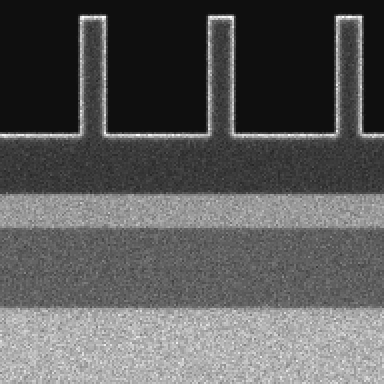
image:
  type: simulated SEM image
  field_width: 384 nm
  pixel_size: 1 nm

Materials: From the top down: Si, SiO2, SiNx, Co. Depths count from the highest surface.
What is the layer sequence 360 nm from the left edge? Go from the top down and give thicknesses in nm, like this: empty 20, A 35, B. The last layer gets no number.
Si 178, SiO2 34, SiNx 80, Co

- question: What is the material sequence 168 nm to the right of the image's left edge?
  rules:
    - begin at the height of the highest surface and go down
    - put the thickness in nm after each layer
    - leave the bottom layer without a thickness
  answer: empty 118, Si 60, SiO2 34, SiNx 80, Co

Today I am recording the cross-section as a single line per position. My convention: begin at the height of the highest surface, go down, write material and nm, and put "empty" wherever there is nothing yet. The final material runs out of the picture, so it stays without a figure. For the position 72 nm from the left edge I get empty 118, Si 60, SiO2 34, SiNx 80, Co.